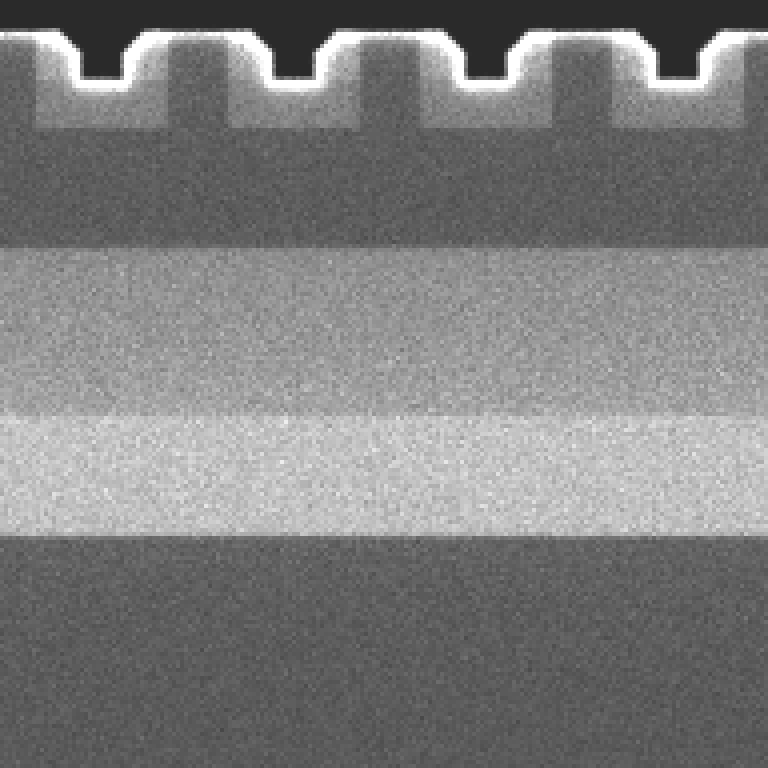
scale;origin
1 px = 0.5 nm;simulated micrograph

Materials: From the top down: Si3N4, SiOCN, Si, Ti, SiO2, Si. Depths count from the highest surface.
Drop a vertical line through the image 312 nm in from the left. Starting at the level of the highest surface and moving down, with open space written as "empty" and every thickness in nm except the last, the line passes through Si3N4 24, SiOCN 24, Si 60, Ti 84, SiO2 60, Si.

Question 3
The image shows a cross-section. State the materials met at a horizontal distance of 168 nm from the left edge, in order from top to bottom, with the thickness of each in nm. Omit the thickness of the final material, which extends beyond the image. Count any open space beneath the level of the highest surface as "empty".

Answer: Si3N4 24, SiOCN 24, Si 60, Ti 84, SiO2 60, Si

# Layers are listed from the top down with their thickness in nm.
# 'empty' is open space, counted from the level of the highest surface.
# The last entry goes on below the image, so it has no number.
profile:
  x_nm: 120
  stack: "Si3N4 24, SiOCN 24, Si 60, Ti 84, SiO2 60, Si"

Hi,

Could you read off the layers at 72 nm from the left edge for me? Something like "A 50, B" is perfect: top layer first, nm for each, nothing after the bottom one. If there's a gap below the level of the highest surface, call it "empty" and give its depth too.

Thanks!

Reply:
Si3N4 24, SiOCN 24, Si 60, Ti 84, SiO2 60, Si